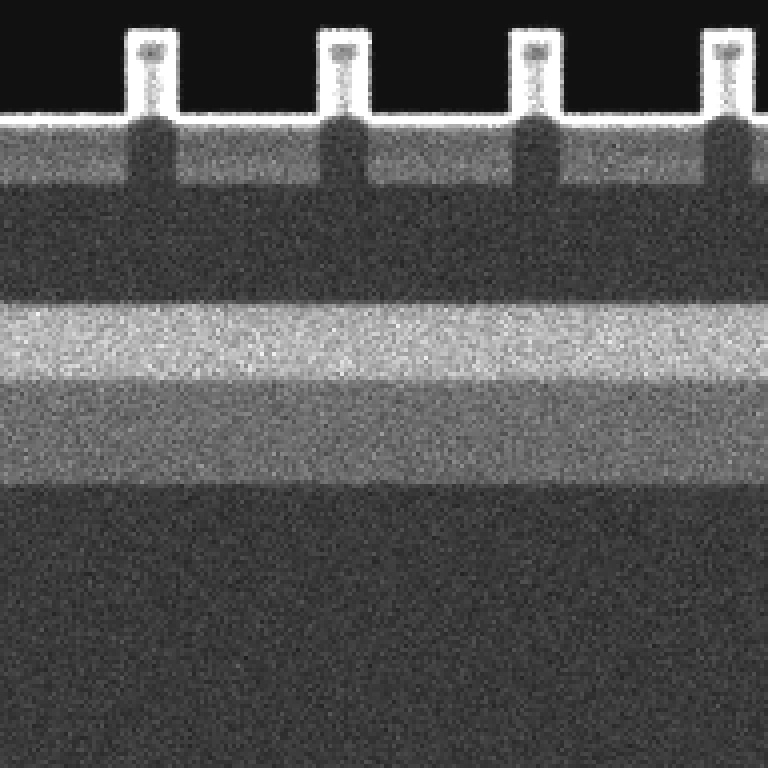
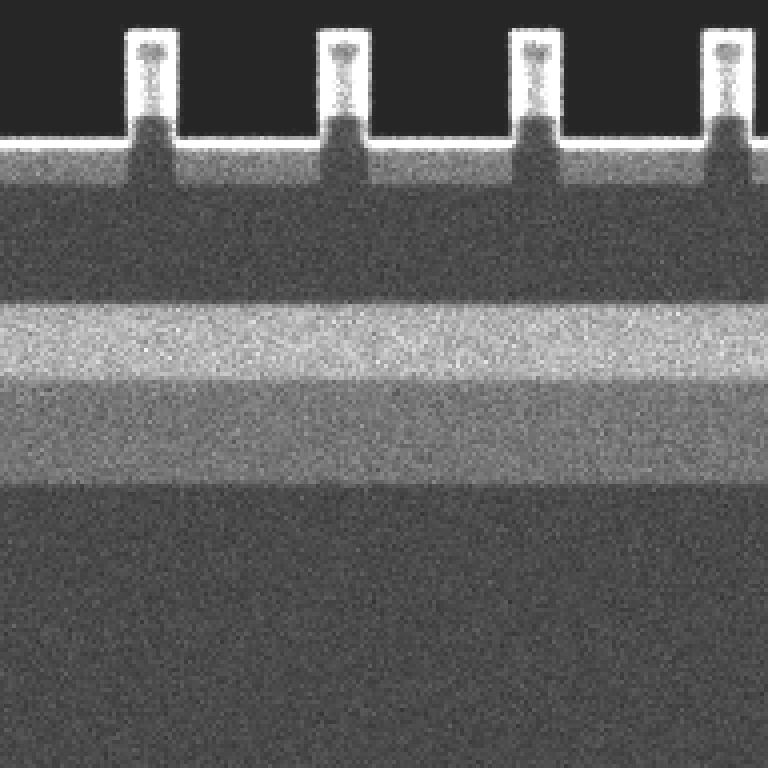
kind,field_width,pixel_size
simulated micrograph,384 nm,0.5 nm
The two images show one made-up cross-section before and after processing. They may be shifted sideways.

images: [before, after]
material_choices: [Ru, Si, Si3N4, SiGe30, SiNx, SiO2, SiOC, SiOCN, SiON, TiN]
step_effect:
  removed: SiNx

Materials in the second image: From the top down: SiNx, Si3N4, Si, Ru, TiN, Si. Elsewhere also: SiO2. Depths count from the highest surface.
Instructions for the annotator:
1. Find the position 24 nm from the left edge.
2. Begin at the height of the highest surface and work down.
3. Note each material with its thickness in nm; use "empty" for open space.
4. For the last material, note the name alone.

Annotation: empty 54, SiNx 8, Si3N4 14, Si 60, Ru 38, TiN 52, Si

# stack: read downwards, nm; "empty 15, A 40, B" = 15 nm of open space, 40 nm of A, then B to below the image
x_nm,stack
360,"Si3N4 14, SiO2 28, Si 94, Ru 38, TiN 52, Si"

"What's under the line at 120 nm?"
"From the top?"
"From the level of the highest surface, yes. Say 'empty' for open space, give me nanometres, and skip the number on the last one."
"empty 54, SiNx 8, Si3N4 14, Si 60, Ru 38, TiN 52, Si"